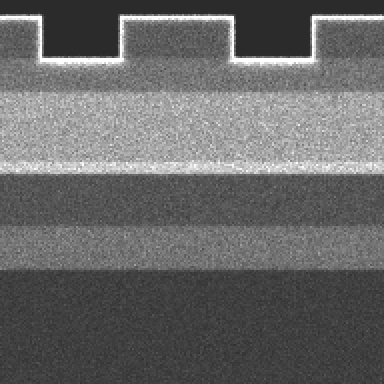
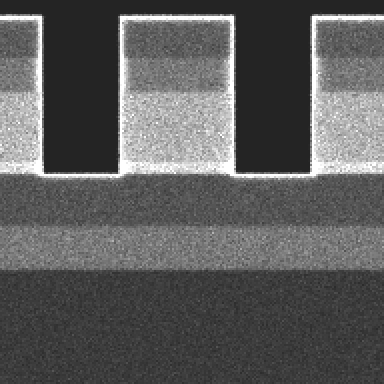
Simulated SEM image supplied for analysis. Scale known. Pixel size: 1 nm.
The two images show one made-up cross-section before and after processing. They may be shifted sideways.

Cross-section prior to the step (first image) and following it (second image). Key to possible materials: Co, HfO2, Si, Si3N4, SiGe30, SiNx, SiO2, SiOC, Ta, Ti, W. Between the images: HfO2 and SiO2 and W was removed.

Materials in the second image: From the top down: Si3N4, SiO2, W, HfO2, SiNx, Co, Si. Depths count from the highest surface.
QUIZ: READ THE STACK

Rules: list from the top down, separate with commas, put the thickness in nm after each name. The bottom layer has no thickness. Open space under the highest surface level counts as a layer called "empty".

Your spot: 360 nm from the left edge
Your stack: Si3N4 42, SiO2 34, W 70, HfO2 12, SiNx 52, Co 44, Si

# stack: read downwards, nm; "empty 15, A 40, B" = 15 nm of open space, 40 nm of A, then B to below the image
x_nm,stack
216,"Si3N4 42, SiO2 34, W 70, HfO2 12, SiNx 52, Co 44, Si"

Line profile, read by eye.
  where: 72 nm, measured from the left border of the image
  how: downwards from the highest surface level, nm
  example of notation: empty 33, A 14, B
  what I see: empty 158, SiNx 52, Co 44, Si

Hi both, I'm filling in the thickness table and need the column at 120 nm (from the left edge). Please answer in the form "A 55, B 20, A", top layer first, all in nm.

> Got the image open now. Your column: Si3N4 42, SiO2 34, W 70, HfO2 12, SiNx 52, Co 44, Si